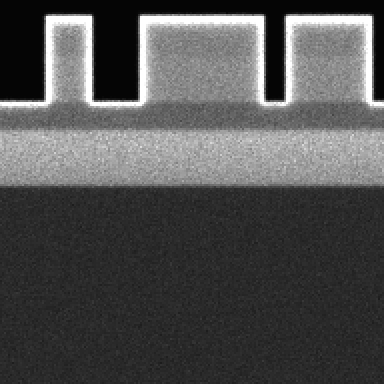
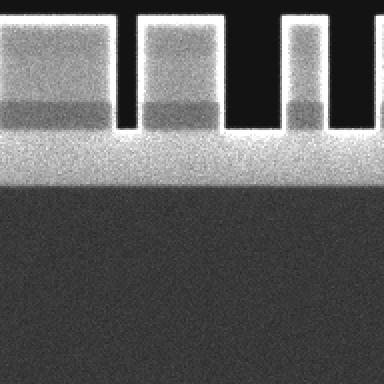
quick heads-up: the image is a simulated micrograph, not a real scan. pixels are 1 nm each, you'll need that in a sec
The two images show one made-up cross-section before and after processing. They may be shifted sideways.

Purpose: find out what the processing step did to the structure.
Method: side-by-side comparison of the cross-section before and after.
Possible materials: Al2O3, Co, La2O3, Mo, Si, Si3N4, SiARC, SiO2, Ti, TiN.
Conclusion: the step removed Si3N4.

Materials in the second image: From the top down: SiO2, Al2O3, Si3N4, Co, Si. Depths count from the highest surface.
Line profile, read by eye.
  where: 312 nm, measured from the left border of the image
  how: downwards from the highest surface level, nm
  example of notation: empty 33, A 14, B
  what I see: SiO2 40, Al2O3 46, Si3N4 28, Co 56, Si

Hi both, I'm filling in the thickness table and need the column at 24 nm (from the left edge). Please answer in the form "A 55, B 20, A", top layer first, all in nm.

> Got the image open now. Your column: SiO2 40, Al2O3 46, Si3N4 28, Co 56, Si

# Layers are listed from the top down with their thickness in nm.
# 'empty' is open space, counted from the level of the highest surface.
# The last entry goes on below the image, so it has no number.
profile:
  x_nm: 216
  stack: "SiO2 40, Al2O3 46, Si3N4 28, Co 56, Si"